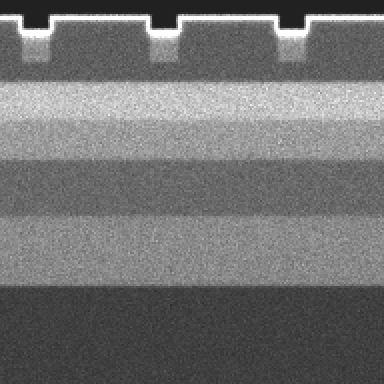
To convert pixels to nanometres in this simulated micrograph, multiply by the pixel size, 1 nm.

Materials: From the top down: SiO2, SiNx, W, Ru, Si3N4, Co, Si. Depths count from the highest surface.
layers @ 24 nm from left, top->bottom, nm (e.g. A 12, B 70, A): empty 14, SiO2 32, SiNx 20, W 38, Ru 40, Si3N4 56, Co 70, Si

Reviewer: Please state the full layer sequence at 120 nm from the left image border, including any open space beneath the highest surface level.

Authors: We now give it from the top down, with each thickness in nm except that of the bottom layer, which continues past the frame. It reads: SiNx 66, W 38, Ru 40, Si3N4 56, Co 70, Si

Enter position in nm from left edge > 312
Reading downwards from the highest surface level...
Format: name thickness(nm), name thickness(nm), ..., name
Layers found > SiNx 66, W 38, Ru 40, Si3N4 56, Co 70, Si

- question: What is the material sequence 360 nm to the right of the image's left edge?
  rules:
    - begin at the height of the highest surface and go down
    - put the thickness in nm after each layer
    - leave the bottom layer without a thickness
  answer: SiNx 66, W 38, Ru 40, Si3N4 56, Co 70, Si